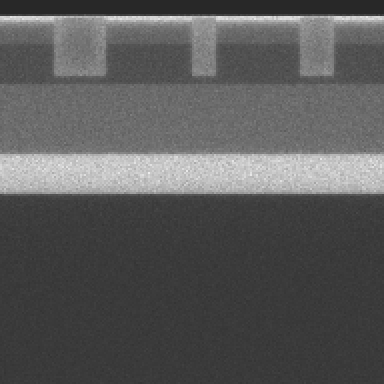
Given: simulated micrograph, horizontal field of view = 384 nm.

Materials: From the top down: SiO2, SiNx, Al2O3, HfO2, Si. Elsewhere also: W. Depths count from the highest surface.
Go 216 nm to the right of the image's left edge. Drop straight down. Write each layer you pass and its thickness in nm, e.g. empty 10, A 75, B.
SiO2 28, SiNx 40, Al2O3 70, HfO2 40, Si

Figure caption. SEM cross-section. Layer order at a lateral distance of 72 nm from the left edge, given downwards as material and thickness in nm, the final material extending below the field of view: W 60, SiNx 8, Al2O3 70, HfO2 40, Si